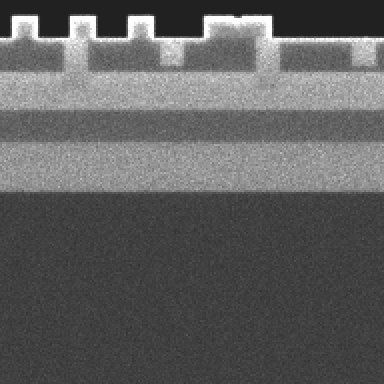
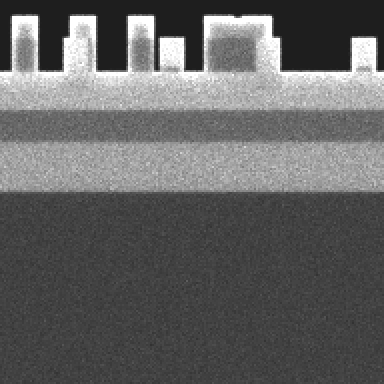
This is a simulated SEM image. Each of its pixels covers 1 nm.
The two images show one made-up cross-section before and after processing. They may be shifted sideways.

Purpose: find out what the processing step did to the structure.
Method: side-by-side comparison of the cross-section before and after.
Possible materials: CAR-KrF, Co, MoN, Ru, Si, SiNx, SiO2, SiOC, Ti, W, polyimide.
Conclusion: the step removed SiNx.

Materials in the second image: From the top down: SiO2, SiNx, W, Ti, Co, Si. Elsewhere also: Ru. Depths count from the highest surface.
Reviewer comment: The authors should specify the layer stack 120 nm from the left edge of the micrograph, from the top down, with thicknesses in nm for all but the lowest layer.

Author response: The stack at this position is empty 56, W 38, Ti 32, Co 50, Si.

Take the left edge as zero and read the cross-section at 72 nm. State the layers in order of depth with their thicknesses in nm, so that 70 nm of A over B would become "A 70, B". SiO2 22, Ru 52, W 20, Ti 32, Co 50, Si